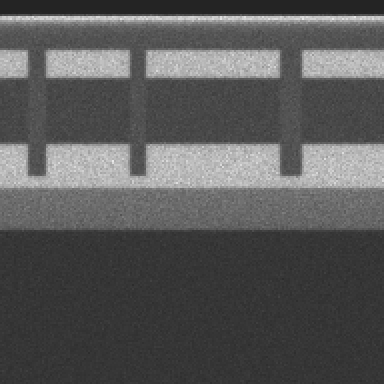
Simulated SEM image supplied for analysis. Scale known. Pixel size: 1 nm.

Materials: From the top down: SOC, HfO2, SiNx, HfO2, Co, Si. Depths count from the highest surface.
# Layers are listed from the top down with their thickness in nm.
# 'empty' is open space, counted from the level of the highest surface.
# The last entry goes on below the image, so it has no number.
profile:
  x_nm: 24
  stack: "SOC 34, HfO2 28, SiNx 66, HfO2 44, Co 42, Si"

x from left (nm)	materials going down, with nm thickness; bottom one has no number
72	SOC 34, HfO2 28, SiNx 66, HfO2 44, Co 42, Si